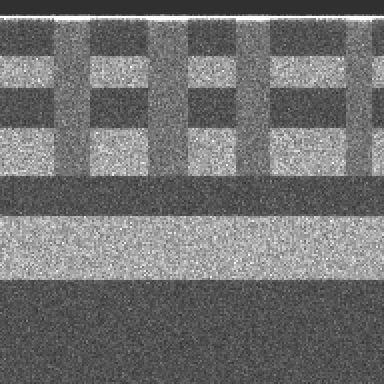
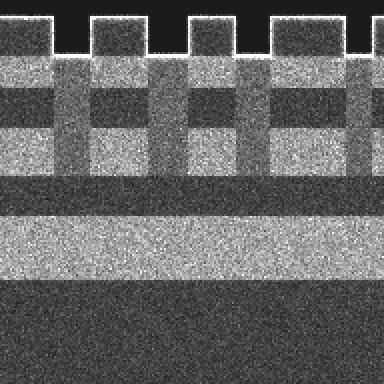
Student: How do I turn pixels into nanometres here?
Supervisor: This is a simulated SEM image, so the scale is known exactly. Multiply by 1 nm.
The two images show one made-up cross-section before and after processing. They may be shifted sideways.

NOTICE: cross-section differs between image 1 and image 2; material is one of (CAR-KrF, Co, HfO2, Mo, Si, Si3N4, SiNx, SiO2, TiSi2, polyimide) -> removed: SiNx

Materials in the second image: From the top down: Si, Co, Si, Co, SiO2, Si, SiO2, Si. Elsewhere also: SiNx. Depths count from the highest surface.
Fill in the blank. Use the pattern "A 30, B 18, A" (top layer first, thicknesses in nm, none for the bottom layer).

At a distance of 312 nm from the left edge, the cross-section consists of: Si 40, Co 32, Si 40, Co 32, SiO2 16, Si 40, SiO2 64, Si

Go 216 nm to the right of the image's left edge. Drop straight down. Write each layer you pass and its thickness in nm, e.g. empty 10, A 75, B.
Si 40, Co 32, Si 40, Co 32, SiO2 16, Si 40, SiO2 64, Si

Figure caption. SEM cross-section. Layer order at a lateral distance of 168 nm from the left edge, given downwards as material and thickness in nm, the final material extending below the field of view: empty 38, SiNx 122, Si 40, SiO2 64, Si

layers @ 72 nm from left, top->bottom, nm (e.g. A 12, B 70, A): empty 38, SiNx 122, Si 40, SiO2 64, Si